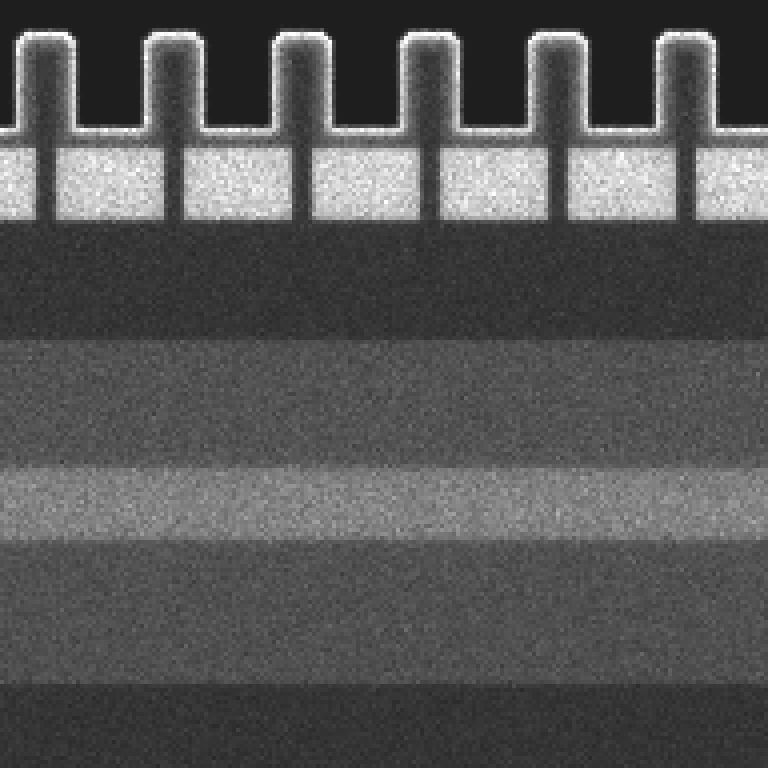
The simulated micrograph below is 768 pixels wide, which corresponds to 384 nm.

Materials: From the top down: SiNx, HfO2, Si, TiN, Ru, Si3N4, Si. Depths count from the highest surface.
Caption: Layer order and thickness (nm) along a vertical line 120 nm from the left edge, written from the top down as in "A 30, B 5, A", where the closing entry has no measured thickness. empty 48, SiNx 10, HfO2 36, Si 60, TiN 64, Ru 36, Si3N4 72, Si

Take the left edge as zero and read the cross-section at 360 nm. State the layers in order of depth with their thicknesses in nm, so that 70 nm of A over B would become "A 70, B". empty 48, SiNx 10, HfO2 36, Si 60, TiN 64, Ru 36, Si3N4 72, Si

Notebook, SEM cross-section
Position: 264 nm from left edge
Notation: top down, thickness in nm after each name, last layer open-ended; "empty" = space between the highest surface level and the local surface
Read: empty 4, SiNx 54, HfO2 36, Si 60, TiN 64, Ru 36, Si3N4 72, Si